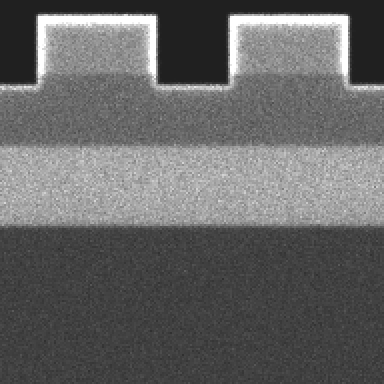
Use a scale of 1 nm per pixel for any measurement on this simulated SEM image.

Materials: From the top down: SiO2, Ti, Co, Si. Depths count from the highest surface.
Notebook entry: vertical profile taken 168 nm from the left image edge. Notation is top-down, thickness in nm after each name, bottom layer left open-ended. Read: empty 70, Ti 60, Co 80, Si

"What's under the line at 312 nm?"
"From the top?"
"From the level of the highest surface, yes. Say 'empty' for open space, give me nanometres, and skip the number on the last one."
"SiO2 58, Ti 72, Co 80, Si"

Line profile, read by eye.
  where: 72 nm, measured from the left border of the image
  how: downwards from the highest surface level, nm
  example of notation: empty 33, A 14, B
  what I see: SiO2 58, Ti 72, Co 80, Si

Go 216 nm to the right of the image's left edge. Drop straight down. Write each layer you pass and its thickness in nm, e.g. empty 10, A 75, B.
empty 70, Ti 60, Co 80, Si